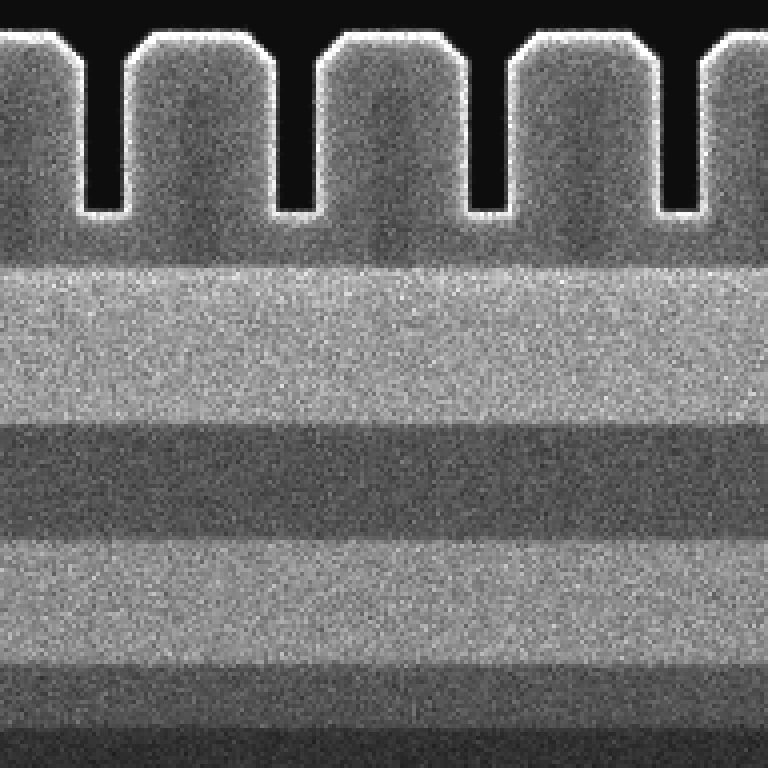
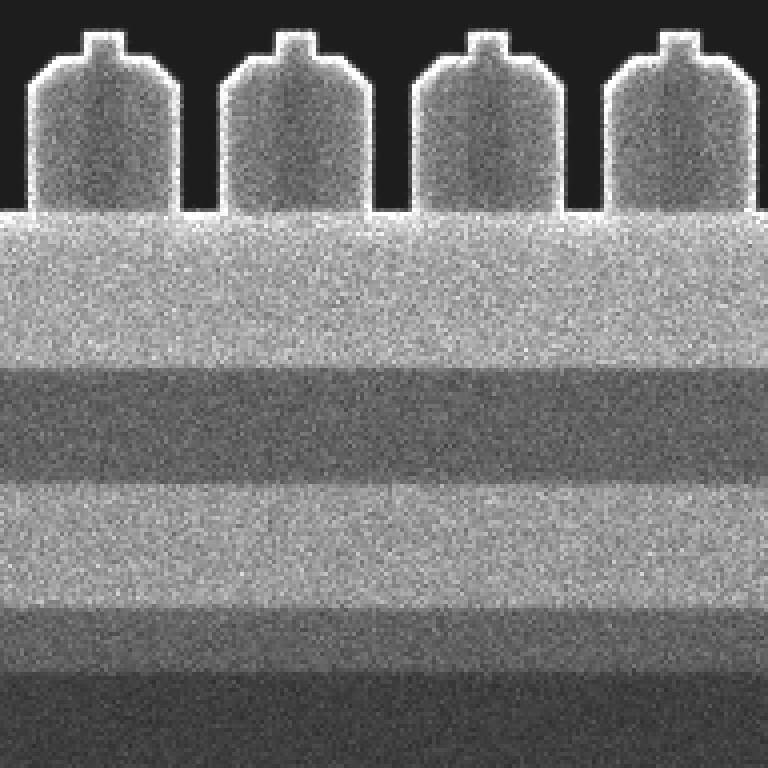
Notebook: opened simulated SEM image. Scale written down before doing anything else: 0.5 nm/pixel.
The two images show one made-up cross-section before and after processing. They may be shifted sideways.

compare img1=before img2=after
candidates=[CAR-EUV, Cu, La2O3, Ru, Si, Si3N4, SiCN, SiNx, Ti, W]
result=removed:Si3N4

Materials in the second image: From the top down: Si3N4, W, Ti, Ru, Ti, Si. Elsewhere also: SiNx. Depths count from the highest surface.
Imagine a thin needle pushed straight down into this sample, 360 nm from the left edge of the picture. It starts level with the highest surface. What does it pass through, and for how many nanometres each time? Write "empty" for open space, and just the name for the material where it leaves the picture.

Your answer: empty 12, Si3N4 78, W 78, Ti 58, Ru 62, Ti 32, Si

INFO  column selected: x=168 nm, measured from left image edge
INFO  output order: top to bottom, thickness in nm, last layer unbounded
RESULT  empty 12, Si3N4 78, W 78, Ti 58, Ru 62, Ti 32, Si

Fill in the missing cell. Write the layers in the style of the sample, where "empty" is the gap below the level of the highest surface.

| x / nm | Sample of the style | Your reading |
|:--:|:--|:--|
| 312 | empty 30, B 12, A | empty 16, Si3N4 74, W 78, Ti 58, Ru 62, Ti 32, Si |